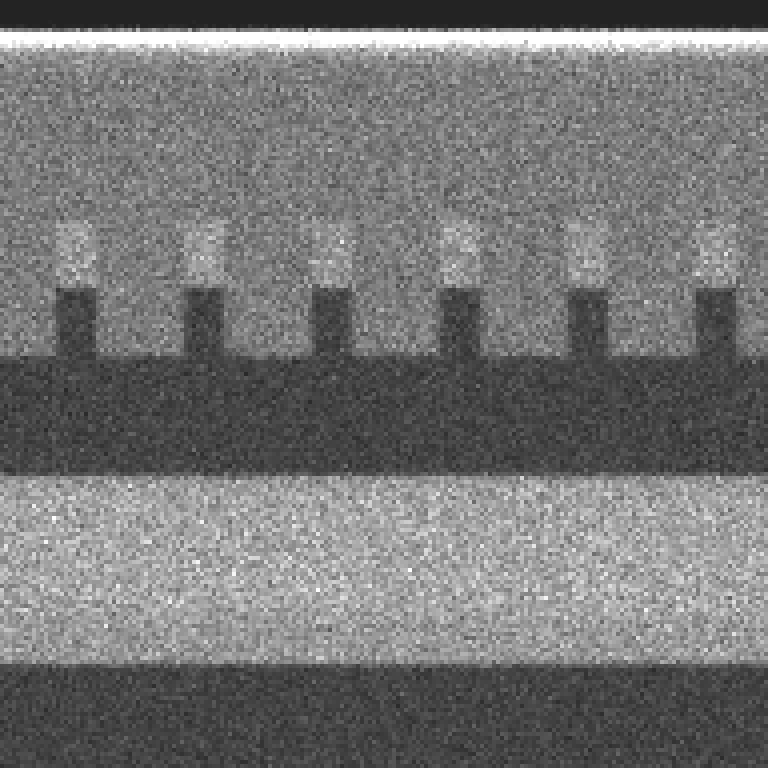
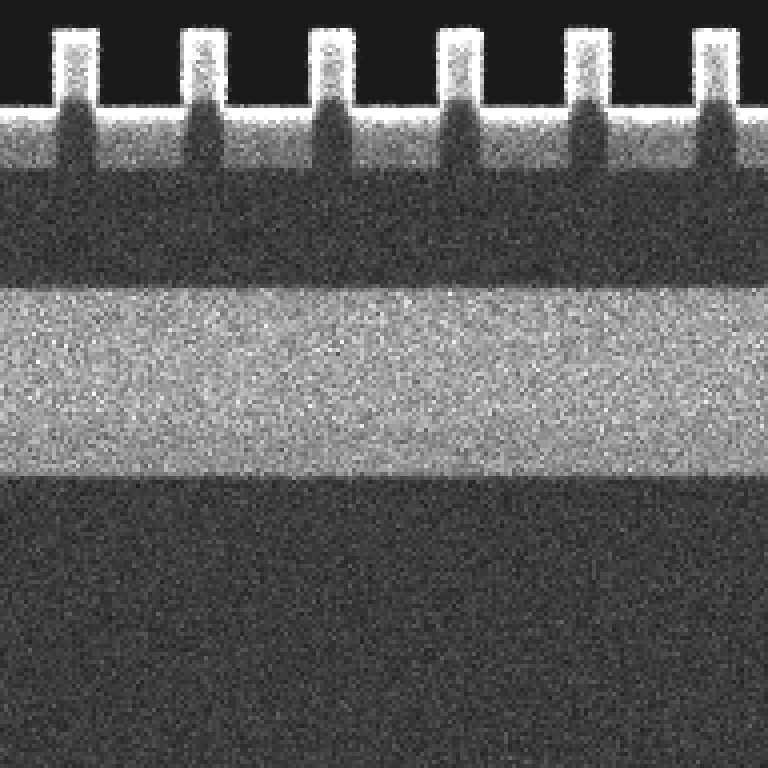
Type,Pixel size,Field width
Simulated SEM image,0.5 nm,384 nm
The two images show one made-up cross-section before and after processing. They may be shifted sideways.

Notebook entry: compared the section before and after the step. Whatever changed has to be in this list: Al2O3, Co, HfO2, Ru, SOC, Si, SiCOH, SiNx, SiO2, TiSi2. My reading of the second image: SOC removed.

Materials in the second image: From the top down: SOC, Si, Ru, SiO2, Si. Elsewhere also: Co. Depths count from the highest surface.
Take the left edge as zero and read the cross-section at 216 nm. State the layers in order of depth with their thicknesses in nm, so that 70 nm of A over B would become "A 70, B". empty 38, SOC 30, Si 60, Ru 70, SiO2 24, Si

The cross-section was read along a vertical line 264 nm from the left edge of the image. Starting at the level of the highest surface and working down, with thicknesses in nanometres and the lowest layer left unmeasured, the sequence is empty 38, SOC 30, Si 60, Ru 70, SiO2 24, Si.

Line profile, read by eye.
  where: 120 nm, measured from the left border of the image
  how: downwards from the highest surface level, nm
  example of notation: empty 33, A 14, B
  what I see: empty 38, SOC 30, Si 60, Ru 70, SiO2 24, Si